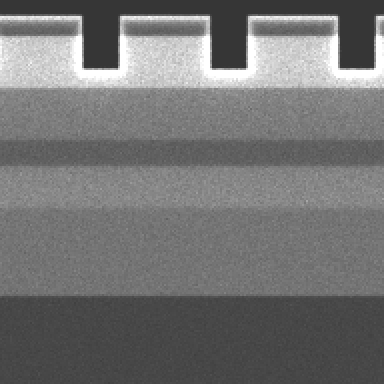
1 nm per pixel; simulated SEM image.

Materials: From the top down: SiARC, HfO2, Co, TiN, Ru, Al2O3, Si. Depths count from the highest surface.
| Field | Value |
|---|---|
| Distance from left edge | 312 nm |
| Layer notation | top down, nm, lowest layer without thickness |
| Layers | SiARC 20, HfO2 52, Co 52, TiN 26, Ru 42, Al2O3 88, Si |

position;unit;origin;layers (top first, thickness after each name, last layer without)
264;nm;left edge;SiARC 20, HfO2 52, Co 52, TiN 26, Ru 42, Al2O3 88, Si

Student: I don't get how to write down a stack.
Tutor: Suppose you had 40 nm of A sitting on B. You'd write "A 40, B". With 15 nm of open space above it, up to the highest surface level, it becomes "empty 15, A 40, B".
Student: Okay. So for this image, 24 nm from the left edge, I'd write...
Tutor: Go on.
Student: SiARC 20, HfO2 52, Co 52, TiN 26, Ru 42, Al2O3 88, Si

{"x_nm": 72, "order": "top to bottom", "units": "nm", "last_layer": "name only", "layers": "SiARC 20, HfO2 52, Co 52, TiN 26, Ru 42, Al2O3 88, Si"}